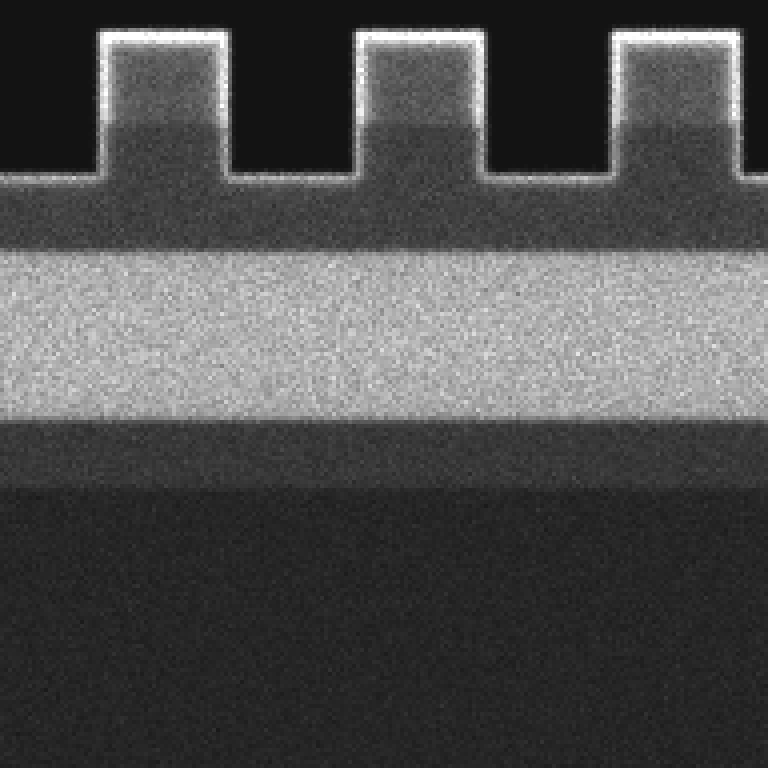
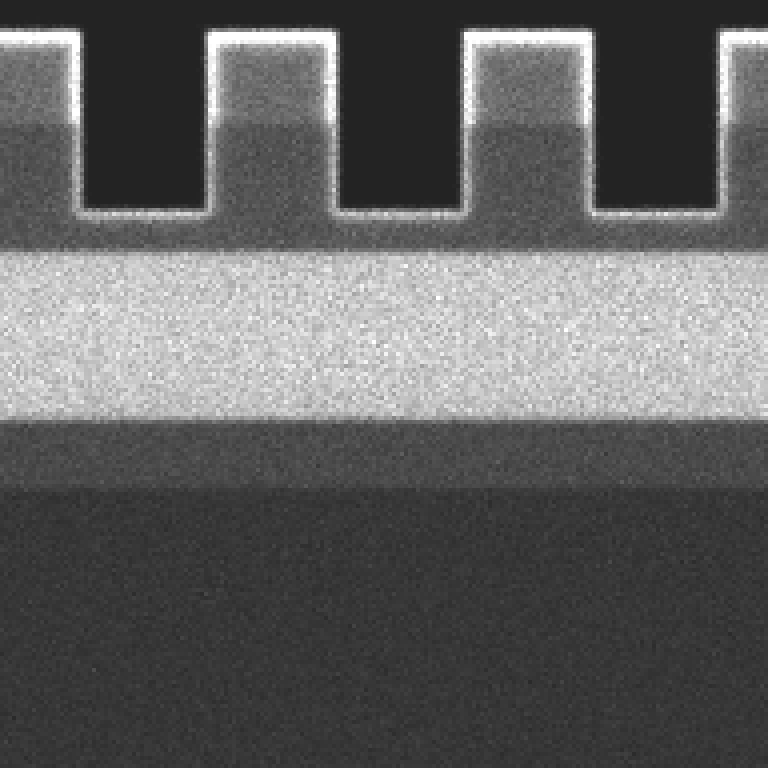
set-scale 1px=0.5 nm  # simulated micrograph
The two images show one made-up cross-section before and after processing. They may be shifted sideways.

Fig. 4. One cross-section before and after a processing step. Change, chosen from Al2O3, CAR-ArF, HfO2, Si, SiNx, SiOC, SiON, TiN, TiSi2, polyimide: TiN removed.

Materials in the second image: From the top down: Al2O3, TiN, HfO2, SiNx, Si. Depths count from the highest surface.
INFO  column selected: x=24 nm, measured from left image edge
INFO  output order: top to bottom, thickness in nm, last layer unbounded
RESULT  Al2O3 46, TiN 64, HfO2 84, SiNx 34, Si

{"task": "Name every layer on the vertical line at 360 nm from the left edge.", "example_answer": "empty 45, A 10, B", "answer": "Al2O3 46, TiN 64, HfO2 84, SiNx 34, Si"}